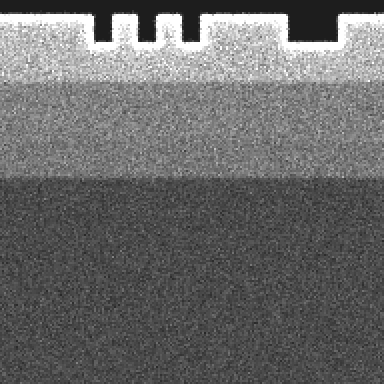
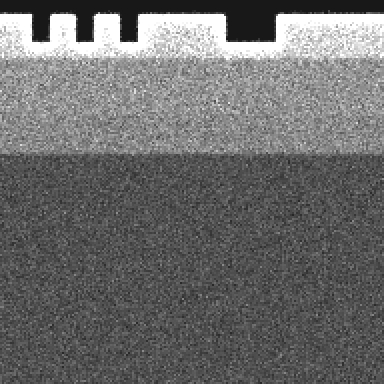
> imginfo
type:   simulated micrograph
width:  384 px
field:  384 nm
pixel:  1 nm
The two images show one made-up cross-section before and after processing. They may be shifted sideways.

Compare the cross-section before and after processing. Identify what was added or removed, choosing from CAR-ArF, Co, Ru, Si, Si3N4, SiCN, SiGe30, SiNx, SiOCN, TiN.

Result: Co removed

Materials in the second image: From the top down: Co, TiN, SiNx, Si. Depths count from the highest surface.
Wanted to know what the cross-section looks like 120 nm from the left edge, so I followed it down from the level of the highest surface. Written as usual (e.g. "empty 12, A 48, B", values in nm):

empty 28, Co 14, TiN 58, SiNx 38, Si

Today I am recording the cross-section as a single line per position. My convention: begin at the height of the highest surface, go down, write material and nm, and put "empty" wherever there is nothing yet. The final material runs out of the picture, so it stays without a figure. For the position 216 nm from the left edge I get Co 42, TiN 58, SiNx 38, Si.